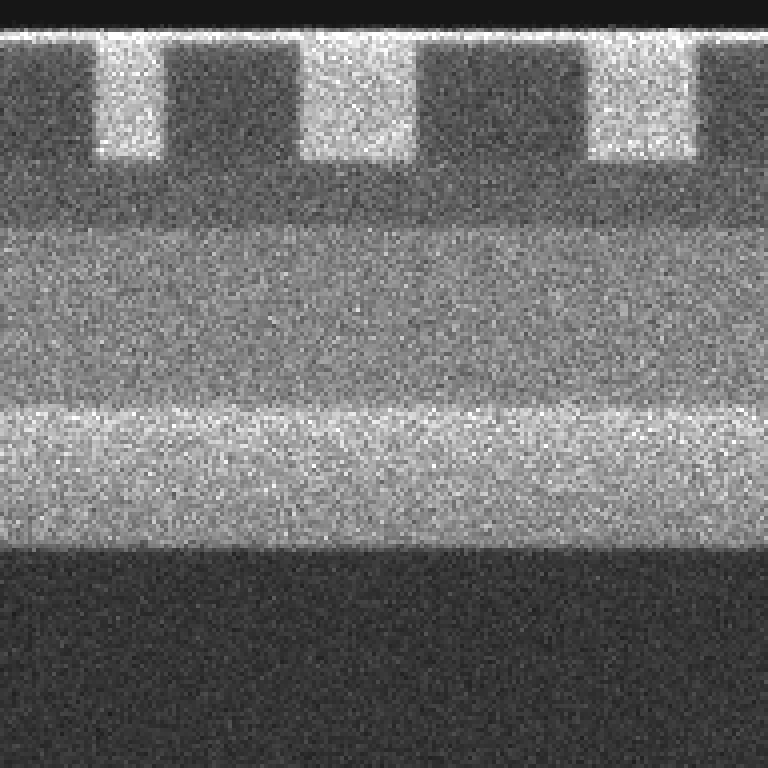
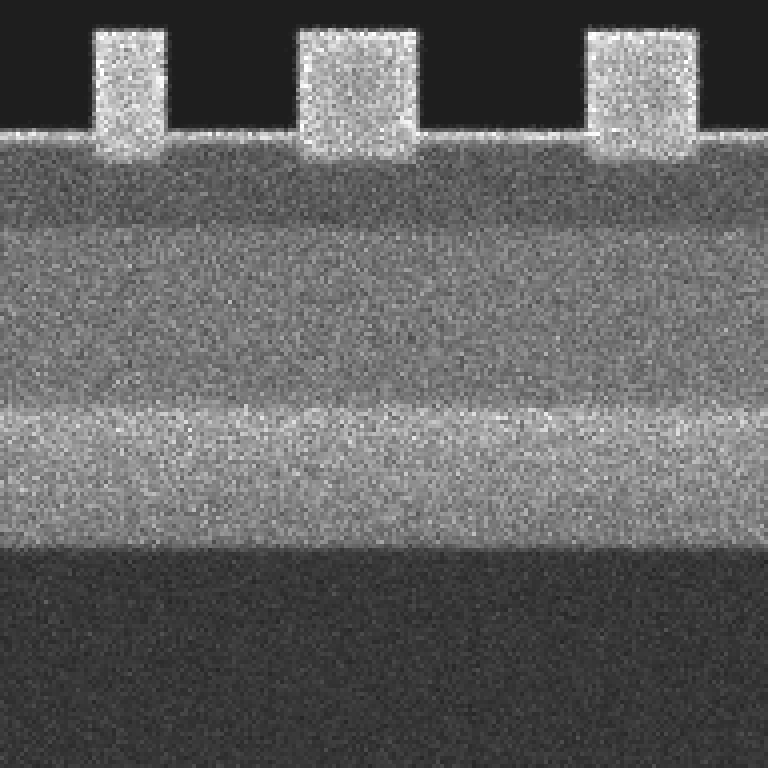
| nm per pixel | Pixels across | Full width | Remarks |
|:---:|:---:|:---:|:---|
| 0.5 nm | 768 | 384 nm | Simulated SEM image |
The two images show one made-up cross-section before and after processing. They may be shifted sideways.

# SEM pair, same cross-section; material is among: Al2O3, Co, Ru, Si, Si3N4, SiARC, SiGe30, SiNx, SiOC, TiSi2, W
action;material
removed;SiNx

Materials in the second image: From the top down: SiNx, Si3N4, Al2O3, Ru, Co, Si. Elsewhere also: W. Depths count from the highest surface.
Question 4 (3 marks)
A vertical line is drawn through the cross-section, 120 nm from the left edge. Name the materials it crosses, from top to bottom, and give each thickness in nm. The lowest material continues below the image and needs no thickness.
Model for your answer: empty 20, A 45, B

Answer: empty 50, SiNx 14, Si3N4 34, Al2O3 90, Ru 44, Co 26, Si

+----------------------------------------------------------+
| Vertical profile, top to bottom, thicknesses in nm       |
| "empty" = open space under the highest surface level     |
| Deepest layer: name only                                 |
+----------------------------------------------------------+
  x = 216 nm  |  empty 50, SiNx 14, Si3N4 34, Al2O3 90, Ru 44, Co 26, Si